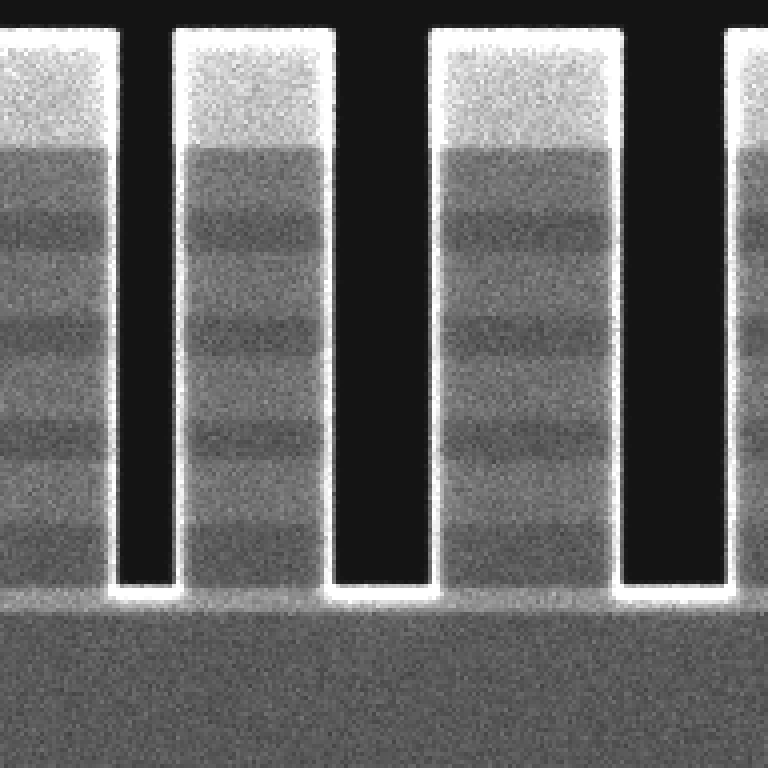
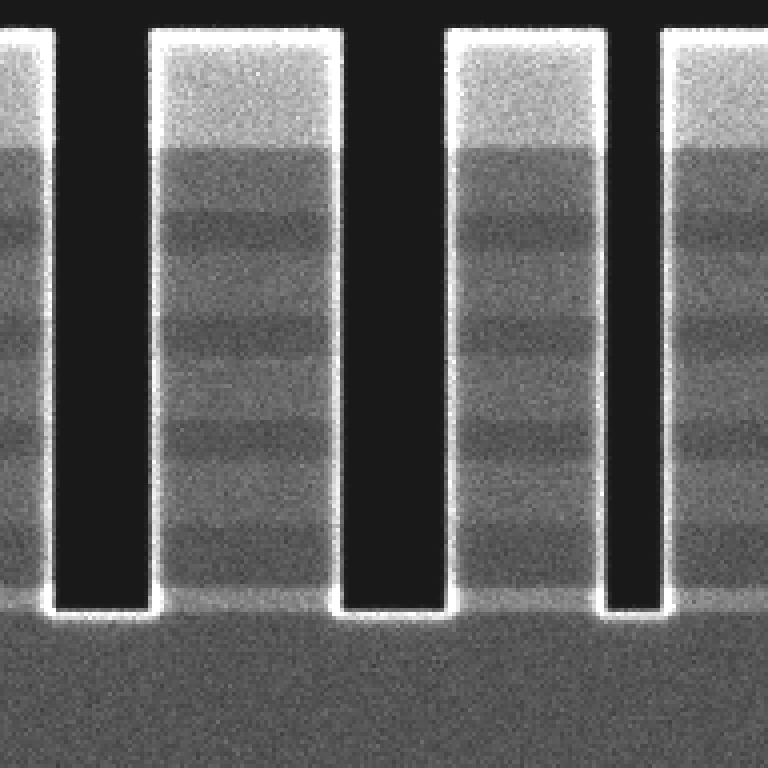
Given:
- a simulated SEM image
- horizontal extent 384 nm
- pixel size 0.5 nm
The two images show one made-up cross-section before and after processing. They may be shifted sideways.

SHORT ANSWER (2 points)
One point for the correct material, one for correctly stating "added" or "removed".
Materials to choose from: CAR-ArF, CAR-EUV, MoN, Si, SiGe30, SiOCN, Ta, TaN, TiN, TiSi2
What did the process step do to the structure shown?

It removed SiOCN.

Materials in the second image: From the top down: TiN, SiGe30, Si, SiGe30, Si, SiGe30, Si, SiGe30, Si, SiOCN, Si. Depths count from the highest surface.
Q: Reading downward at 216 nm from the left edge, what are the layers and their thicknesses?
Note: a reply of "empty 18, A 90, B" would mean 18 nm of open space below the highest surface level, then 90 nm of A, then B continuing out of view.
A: empty 290, Si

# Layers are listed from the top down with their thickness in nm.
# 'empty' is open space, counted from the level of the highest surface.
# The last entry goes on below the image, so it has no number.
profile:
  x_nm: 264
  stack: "TiN 58, SiGe30 32, Si 20, SiGe30 32, Si 20, SiGe30 32, Si 20, SiGe30 32, Si 32, SiOCN 12, Si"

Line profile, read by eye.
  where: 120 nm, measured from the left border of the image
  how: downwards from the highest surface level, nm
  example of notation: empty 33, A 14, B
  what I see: TiN 58, SiGe30 32, Si 20, SiGe30 32, Si 20, SiGe30 32, Si 20, SiGe30 32, Si 32, SiOCN 12, Si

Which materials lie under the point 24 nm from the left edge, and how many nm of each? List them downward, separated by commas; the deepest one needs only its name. TiN 58, SiGe30 32, Si 20, SiGe30 32, Si 20, SiGe30 32, Si 20, SiGe30 32, Si 32, SiOCN 12, Si